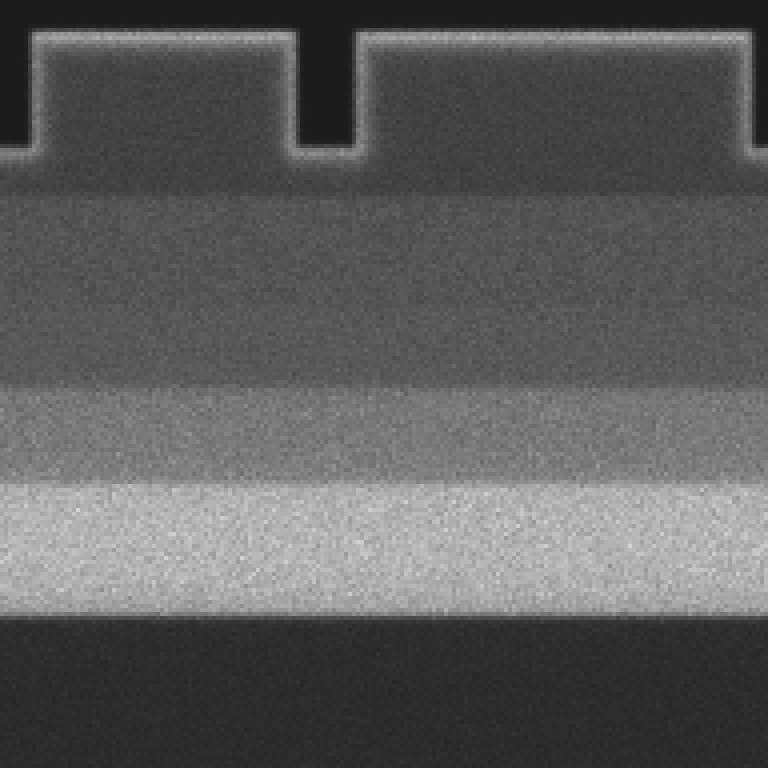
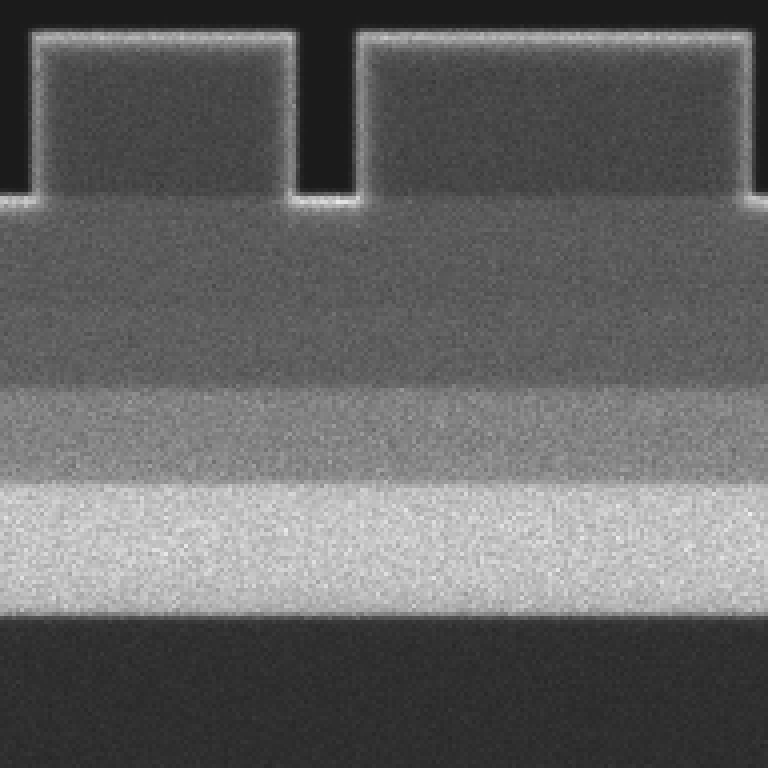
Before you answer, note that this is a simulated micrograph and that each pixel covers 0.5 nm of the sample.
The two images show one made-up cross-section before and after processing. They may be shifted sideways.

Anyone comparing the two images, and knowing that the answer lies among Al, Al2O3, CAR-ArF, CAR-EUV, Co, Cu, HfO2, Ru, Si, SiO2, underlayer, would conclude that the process removed underlayer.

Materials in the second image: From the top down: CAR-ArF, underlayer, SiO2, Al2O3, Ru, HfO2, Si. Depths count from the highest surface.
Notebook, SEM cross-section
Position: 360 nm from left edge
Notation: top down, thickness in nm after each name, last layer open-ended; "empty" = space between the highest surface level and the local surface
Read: CAR-ArF 58, underlayer 24, SiO2 56, Al2O3 40, Ru 48, HfO2 66, Si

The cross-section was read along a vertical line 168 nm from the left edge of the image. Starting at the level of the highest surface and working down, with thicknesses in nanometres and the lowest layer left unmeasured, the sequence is empty 82, SiO2 56, Al2O3 40, Ru 48, HfO2 66, Si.